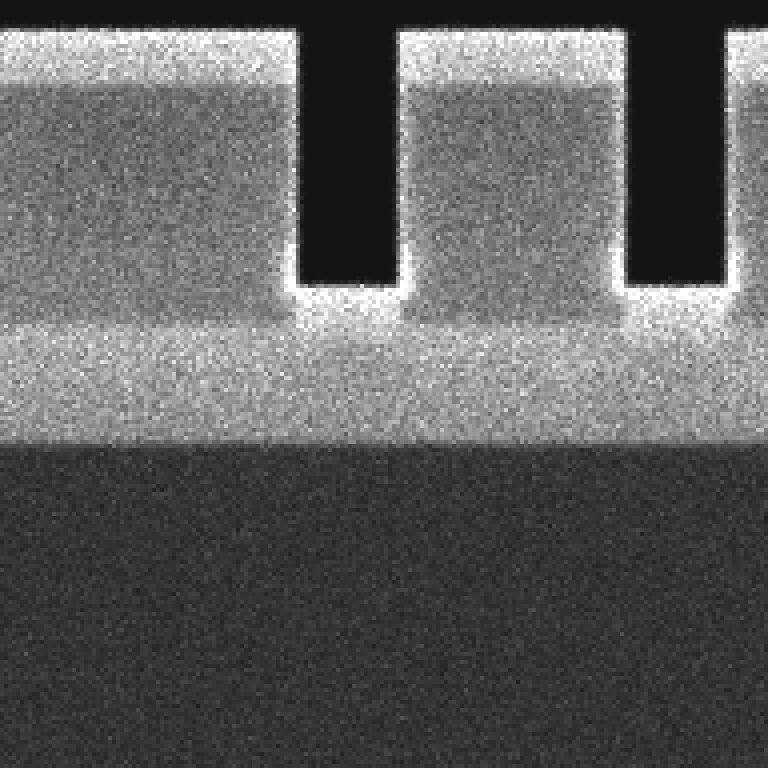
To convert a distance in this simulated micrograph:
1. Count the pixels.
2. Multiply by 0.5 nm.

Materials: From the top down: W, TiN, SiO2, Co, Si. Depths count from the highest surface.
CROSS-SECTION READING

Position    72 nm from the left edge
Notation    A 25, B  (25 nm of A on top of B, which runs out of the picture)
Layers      W 26, TiN 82, SiO2 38, Co 60, Si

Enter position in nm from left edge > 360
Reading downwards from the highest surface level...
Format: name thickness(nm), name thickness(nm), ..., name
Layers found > empty 128, W 26, Co 52, Si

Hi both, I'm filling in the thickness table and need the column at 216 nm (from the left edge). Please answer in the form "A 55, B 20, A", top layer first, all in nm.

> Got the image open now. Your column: W 26, TiN 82, SiO2 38, Co 60, Si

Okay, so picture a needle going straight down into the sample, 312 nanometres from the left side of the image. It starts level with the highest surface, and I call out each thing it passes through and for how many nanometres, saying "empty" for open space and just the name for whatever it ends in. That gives empty 128, W 26, Co 52, Si